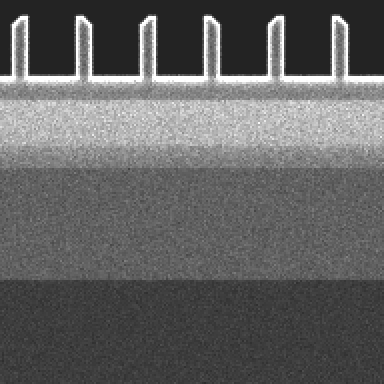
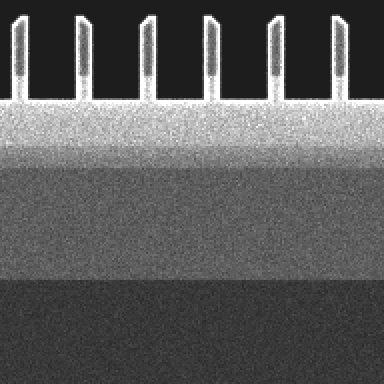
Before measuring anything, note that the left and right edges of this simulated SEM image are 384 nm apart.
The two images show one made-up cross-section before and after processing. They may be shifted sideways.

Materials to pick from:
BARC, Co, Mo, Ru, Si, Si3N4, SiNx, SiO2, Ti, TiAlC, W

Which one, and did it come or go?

SiO2 - removed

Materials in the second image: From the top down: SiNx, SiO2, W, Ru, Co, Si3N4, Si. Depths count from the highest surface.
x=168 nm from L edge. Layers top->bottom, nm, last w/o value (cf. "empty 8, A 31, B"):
empty 84, W 46, Ru 10, Co 12, Si3N4 112, Si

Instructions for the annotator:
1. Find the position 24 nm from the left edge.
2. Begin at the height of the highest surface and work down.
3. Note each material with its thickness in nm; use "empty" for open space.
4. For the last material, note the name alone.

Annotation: SiNx 60, SiO2 24, W 46, Ru 10, Co 12, Si3N4 112, Si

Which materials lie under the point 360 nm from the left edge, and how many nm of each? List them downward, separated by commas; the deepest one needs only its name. empty 84, W 46, Ru 10, Co 12, Si3N4 112, Si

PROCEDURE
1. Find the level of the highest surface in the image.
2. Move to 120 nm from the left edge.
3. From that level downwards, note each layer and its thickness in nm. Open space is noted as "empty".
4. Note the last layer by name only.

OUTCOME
empty 84, W 46, Ru 10, Co 12, Si3N4 112, Si